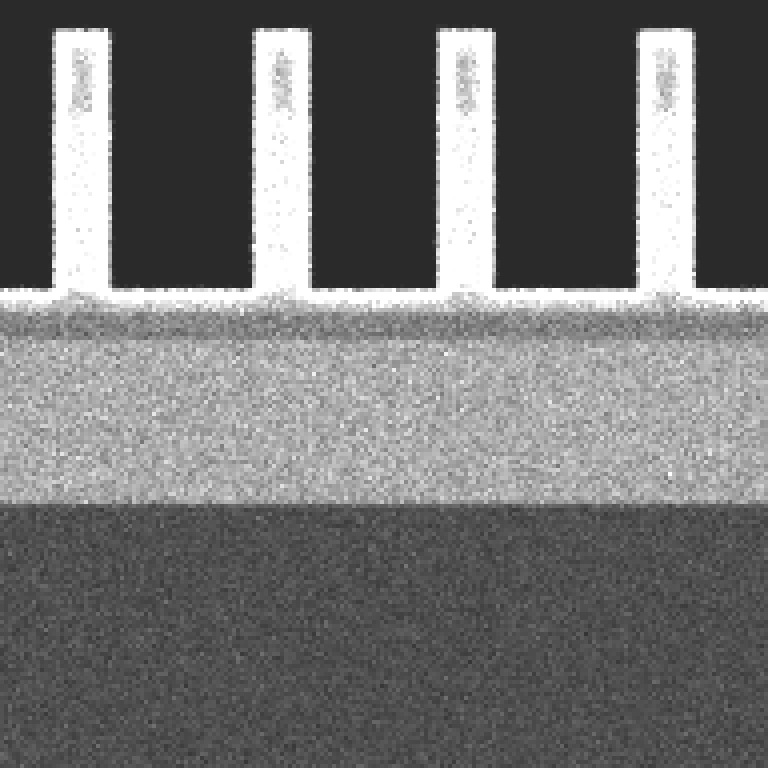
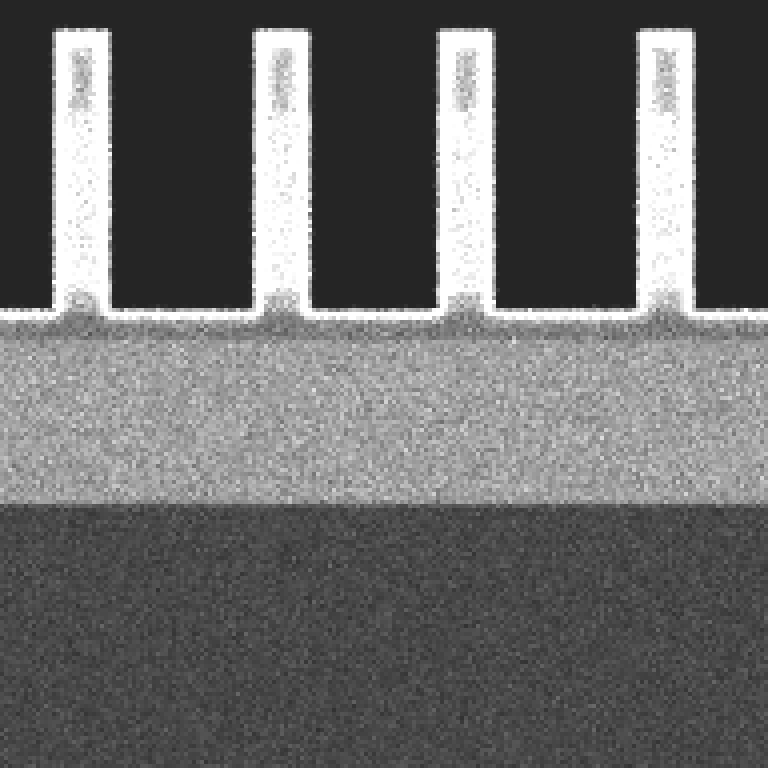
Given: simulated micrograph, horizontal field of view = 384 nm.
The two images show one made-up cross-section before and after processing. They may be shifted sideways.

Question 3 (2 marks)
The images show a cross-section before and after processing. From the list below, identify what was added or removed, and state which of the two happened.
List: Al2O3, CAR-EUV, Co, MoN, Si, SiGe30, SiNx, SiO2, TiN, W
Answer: Co was removed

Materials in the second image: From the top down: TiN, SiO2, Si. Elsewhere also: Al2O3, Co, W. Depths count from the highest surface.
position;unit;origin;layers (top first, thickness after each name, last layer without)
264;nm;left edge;empty 140, TiN 14, SiO2 82, Si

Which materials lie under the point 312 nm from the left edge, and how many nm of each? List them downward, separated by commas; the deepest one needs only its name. empty 140, TiN 14, SiO2 82, Si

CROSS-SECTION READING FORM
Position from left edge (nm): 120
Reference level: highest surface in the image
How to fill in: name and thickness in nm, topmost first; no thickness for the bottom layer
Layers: empty 140, TiN 14, SiO2 82, Si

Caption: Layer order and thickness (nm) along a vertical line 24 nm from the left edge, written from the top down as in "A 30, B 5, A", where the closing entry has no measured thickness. empty 140, TiN 14, SiO2 82, Si